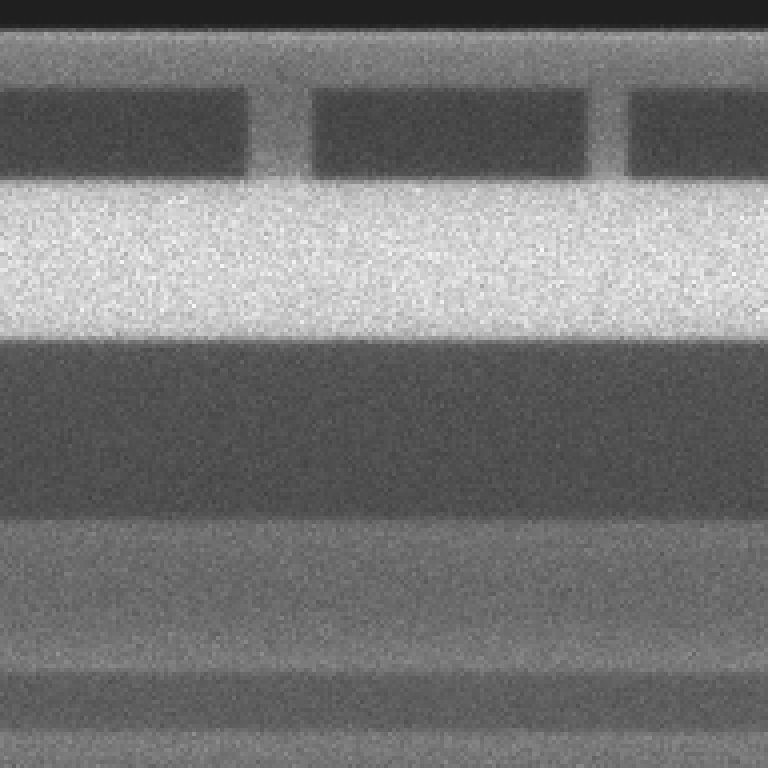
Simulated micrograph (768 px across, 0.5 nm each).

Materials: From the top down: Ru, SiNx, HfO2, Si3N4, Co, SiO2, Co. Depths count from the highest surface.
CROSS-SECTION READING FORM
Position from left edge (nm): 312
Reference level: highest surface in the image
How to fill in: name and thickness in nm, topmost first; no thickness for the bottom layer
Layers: Ru 74, HfO2 80, Si3N4 90, Co 76, SiO2 30, Co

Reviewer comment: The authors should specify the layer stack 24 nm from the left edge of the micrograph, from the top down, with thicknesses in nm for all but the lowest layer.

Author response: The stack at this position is Ru 28, SiNx 46, HfO2 80, Si3N4 90, Co 76, SiO2 30, Co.